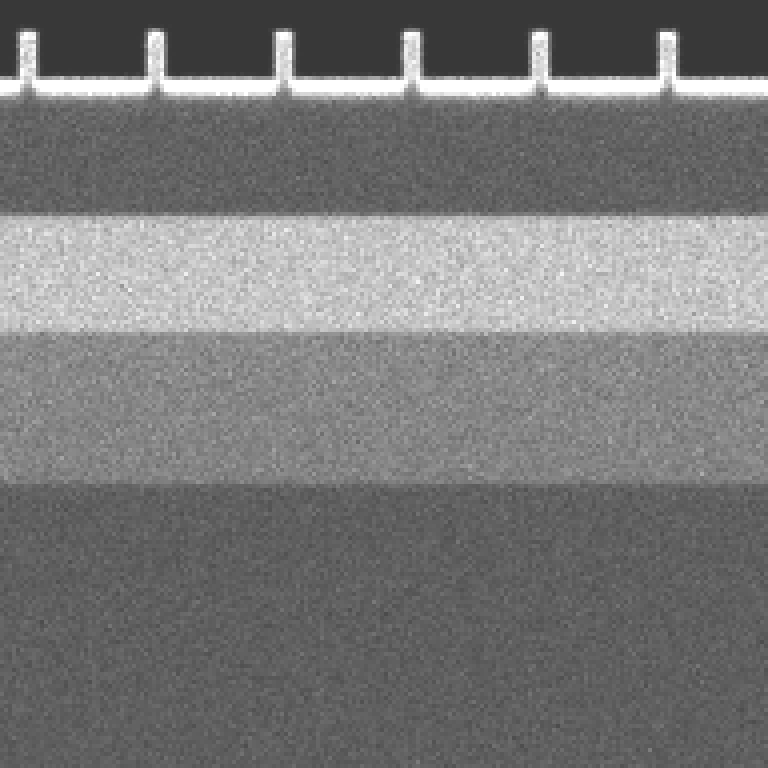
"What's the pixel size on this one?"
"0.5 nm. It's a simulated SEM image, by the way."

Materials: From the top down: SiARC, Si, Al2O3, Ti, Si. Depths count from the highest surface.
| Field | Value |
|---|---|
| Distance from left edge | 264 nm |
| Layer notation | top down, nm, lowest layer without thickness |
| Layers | empty 24, SiARC 8, Si 60, Al2O3 58, Ti 76, Si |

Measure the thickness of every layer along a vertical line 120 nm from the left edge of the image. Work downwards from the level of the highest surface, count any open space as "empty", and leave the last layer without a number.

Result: empty 24, SiARC 8, Si 60, Al2O3 58, Ti 76, Si